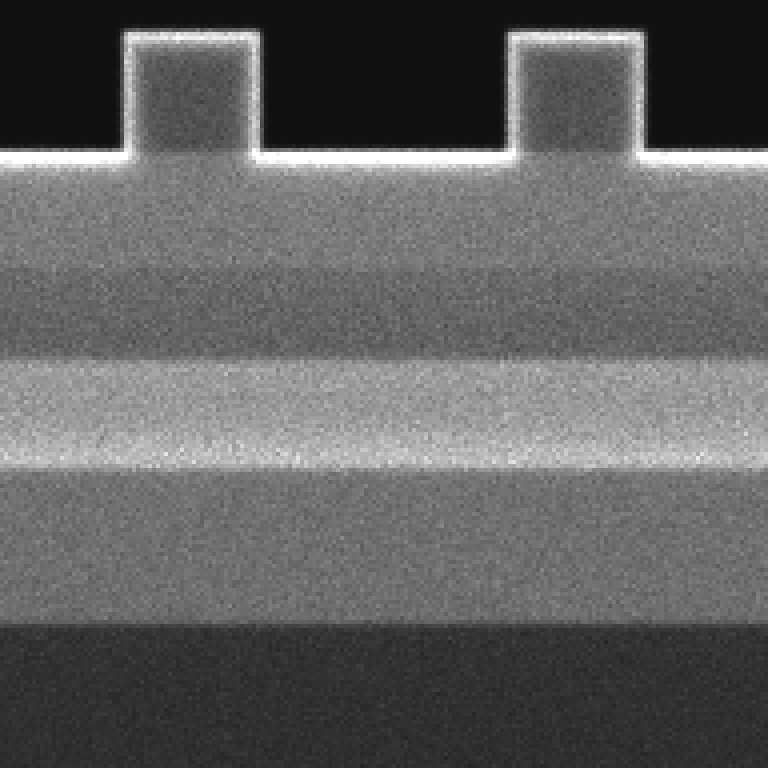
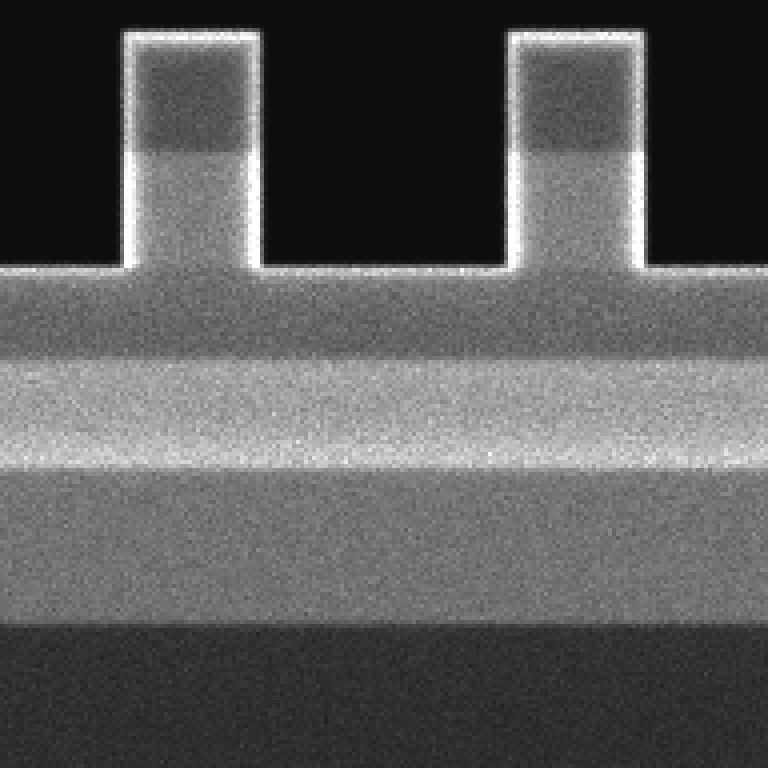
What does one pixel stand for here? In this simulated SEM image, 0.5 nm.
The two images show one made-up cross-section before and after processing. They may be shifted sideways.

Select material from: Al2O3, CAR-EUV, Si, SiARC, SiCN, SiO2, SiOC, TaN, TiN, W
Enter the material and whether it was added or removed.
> Al2O3 / removed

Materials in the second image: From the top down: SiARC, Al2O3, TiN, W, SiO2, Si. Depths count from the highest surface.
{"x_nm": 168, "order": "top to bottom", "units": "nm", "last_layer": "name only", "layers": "empty 118, TiN 46, W 54, SiO2 78, Si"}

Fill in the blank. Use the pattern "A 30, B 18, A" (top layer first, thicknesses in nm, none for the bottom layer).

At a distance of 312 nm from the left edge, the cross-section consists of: SiARC 60, Al2O3 58, TiN 46, W 54, SiO2 78, Si